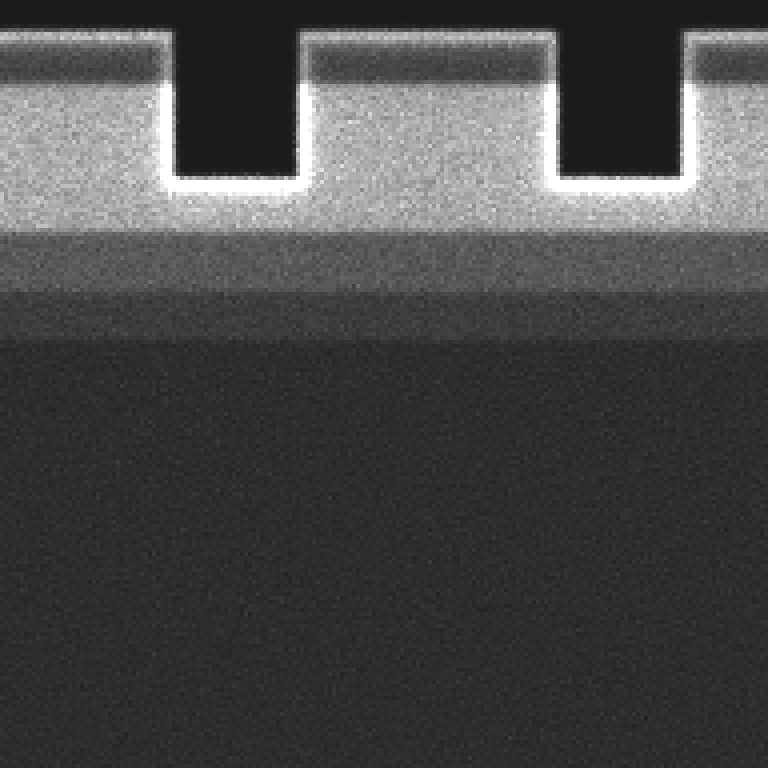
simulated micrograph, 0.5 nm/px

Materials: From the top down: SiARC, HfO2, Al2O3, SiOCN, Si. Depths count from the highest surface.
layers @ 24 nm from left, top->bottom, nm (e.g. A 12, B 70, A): SiARC 26, HfO2 74, Al2O3 30, SiOCN 24, Si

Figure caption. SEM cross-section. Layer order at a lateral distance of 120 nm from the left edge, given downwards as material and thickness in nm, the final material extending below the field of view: empty 74, HfO2 26, Al2O3 30, SiOCN 24, Si